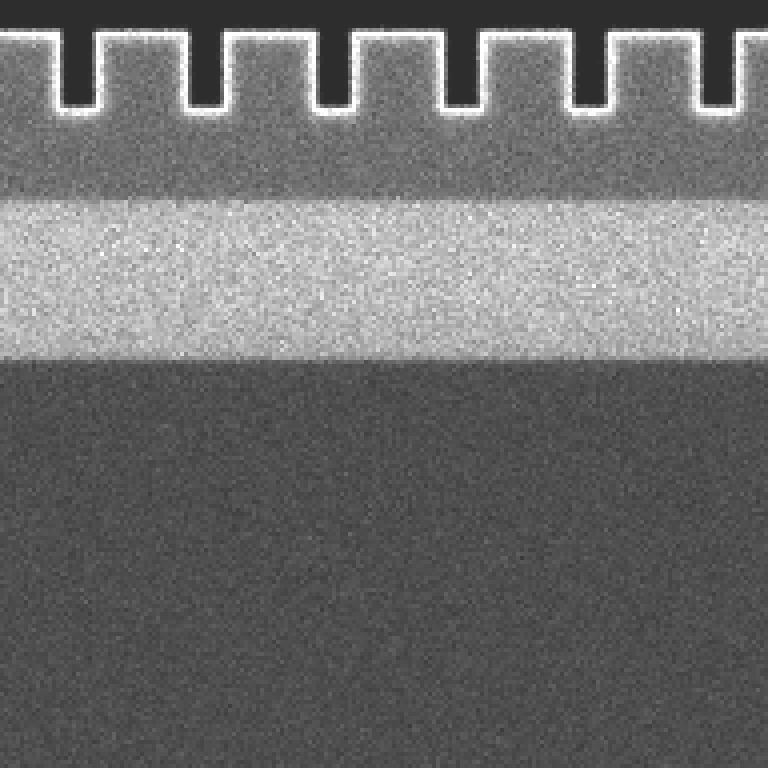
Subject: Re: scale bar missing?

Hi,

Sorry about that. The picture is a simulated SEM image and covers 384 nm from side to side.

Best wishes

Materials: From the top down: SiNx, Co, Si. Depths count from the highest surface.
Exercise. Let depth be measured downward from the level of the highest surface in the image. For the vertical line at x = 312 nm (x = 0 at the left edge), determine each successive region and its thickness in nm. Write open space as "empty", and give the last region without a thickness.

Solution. SiNx 84, Co 80, Si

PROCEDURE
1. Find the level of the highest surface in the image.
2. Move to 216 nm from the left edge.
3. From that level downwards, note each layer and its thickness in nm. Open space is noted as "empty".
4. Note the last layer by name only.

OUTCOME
SiNx 84, Co 80, Si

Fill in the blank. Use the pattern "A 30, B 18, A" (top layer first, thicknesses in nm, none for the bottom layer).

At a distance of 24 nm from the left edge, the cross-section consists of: SiNx 84, Co 80, Si